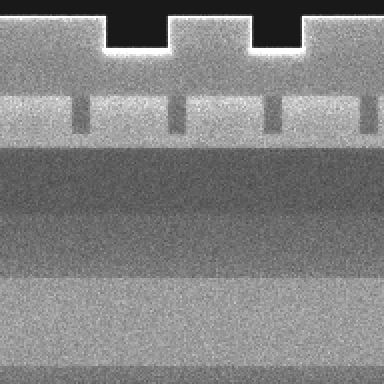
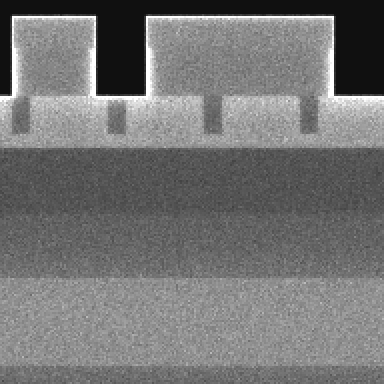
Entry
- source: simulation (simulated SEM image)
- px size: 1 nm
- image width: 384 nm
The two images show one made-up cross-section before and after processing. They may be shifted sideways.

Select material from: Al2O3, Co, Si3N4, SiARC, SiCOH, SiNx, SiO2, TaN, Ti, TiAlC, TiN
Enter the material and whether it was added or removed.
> SiO2 / removed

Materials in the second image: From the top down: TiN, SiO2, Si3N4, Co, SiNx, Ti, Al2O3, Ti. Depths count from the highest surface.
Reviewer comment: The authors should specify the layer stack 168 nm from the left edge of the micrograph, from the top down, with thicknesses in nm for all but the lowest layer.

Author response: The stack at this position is TiN 32, SiO2 48, Co 52, SiNx 66, Ti 64, Al2O3 88, Ti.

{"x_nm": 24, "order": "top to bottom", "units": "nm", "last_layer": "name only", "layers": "TiN 32, SiO2 48, Si3N4 38, Co 14, SiNx 66, Ti 64, Al2O3 88, Ti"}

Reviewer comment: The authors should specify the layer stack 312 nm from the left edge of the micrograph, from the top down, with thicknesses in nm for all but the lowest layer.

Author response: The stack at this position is TiN 32, SiO2 48, Si3N4 38, Co 14, SiNx 66, Ti 64, Al2O3 88, Ti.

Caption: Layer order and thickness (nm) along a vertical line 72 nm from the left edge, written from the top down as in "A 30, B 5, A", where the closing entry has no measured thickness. TiN 32, SiO2 48, Co 52, SiNx 66, Ti 64, Al2O3 88, Ti